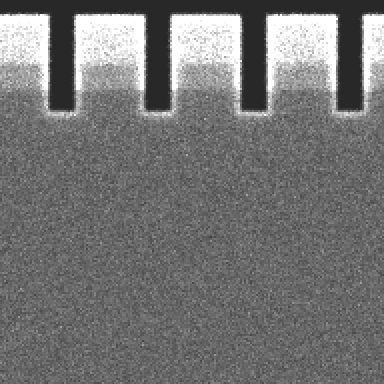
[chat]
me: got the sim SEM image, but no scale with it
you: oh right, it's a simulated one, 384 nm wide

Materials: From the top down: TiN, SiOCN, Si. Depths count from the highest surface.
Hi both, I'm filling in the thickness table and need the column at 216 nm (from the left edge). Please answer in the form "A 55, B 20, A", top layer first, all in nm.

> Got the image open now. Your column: TiN 48, SiOCN 26, Si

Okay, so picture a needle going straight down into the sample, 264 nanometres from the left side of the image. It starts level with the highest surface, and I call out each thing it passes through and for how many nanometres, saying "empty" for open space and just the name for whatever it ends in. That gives empty 96, Si